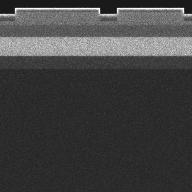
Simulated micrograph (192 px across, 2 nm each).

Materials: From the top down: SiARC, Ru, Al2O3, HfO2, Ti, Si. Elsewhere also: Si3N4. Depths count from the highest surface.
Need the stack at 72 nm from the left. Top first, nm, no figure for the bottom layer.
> Si3N4 8, Ru 26, Al2O3 24, HfO2 38, Ti 26, Si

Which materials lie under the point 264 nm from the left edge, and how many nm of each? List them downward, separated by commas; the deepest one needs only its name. Si3N4 8, Ru 26, Al2O3 24, HfO2 38, Ti 26, Si